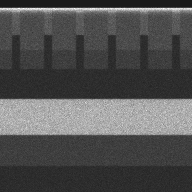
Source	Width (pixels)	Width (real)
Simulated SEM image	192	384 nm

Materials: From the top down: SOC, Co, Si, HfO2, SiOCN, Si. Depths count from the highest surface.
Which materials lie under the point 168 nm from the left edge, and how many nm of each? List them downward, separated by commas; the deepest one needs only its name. SOC 84, SiOCN 38, Si 60, HfO2 72, SiOCN 62, Si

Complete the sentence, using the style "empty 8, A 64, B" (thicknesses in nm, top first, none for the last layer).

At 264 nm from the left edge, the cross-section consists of SOC 84, SiOCN 38, Si 60, HfO2 72, SiOCN 62, Si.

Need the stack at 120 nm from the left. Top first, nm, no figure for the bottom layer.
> SOC 84, SiOCN 38, Si 60, HfO2 72, SiOCN 62, Si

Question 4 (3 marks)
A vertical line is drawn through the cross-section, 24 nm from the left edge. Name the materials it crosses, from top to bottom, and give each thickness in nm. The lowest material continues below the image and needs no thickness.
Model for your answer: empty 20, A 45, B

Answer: SOC 6, Co 48, Si 128, HfO2 72, SiOCN 62, Si